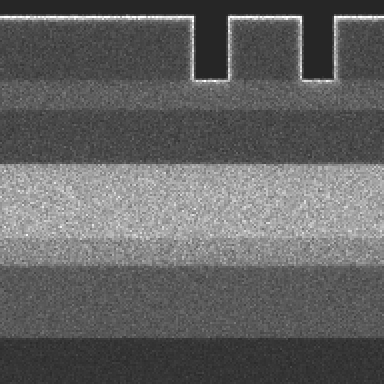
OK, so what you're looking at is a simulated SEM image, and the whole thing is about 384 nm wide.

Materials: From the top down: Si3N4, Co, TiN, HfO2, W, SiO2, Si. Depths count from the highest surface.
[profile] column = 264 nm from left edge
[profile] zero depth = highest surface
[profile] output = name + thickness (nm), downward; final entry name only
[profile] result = Si3N4 64, Co 30, TiN 54, HfO2 74, W 28, SiO2 72, Si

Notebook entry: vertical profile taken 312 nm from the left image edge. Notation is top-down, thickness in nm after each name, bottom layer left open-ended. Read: empty 64, Co 30, TiN 54, HfO2 74, W 28, SiO2 72, Si